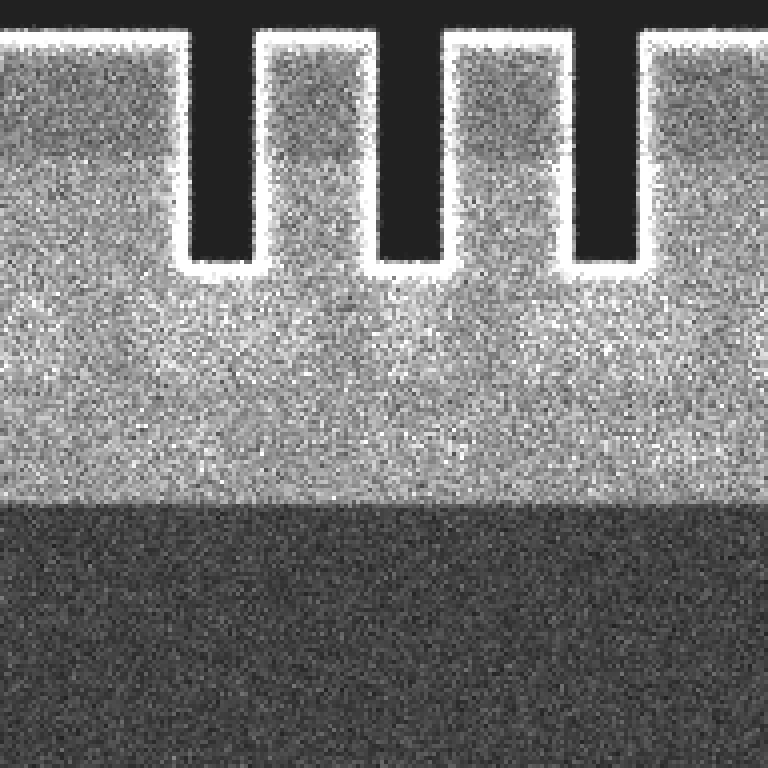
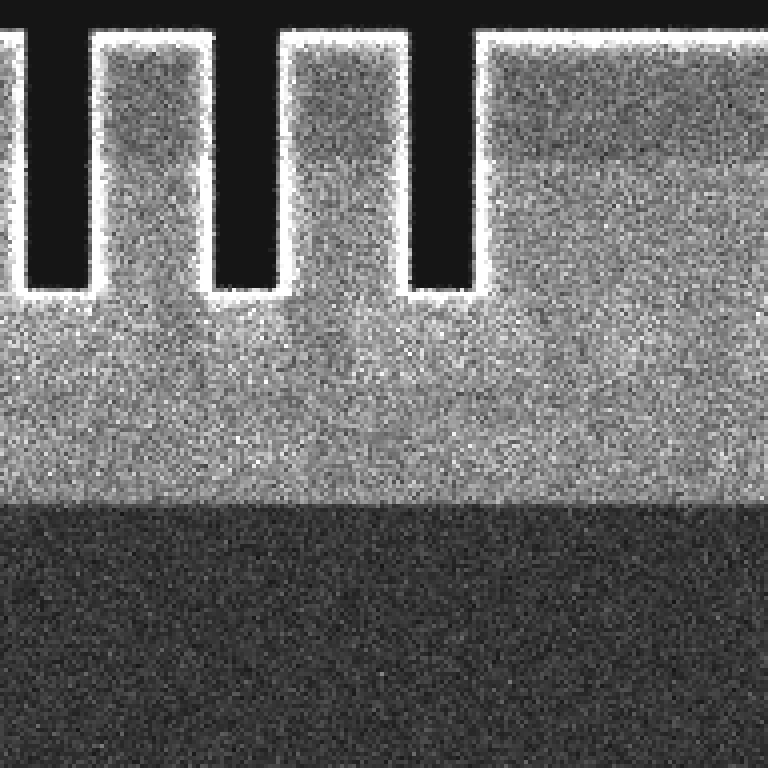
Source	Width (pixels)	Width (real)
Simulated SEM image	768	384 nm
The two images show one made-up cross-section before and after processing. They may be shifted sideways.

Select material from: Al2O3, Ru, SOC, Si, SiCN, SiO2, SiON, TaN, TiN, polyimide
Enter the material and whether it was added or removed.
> Al2O3 / removed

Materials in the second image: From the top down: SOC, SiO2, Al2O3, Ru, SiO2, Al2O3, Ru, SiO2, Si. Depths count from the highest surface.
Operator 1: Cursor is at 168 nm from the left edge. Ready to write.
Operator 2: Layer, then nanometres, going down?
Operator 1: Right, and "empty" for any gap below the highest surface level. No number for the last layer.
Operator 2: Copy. SOC 64, SiO2 52, Al2O3 14, SiO2 60, Al2O3 8, SiO2 38, Si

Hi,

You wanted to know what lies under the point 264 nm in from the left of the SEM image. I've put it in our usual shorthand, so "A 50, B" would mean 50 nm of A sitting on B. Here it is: SOC 64, SiO2 52, Al2O3 14, Ru 46, SiO2 14, Al2O3 8, Ru 24, SiO2 14, Si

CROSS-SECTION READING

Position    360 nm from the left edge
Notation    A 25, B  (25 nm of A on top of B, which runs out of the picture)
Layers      SOC 64, SiO2 52, Al2O3 14, SiO2 60, Al2O3 8, Ru 24, SiO2 14, Si